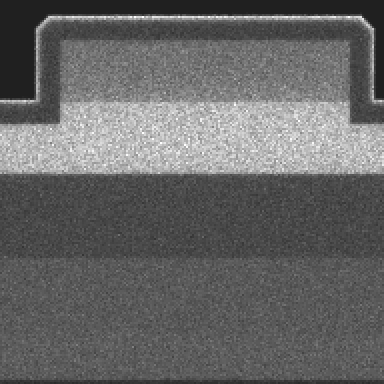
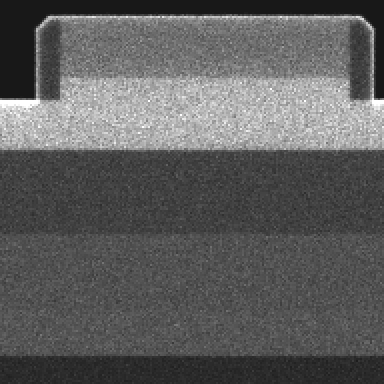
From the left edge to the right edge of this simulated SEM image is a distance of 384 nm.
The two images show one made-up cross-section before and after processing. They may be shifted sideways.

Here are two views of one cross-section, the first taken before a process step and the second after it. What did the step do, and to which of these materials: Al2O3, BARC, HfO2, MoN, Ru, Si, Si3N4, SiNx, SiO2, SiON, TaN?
It removed SiNx.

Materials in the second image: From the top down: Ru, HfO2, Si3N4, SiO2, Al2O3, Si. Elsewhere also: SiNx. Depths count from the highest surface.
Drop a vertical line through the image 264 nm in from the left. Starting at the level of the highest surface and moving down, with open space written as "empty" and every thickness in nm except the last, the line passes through Ru 62, HfO2 72, Si3N4 84, SiO2 76, Al2O3 46, Si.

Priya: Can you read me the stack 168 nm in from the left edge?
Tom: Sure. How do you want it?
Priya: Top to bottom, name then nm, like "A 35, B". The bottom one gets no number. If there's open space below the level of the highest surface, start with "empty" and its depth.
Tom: Ru 62, HfO2 72, Si3N4 84, SiO2 76, Al2O3 46, Si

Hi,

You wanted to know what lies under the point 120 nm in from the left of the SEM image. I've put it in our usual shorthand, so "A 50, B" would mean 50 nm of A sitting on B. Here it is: Ru 62, HfO2 72, Si3N4 84, SiO2 76, Al2O3 46, Si